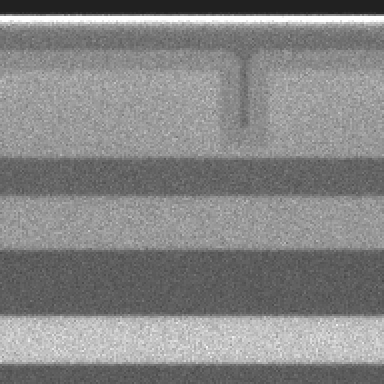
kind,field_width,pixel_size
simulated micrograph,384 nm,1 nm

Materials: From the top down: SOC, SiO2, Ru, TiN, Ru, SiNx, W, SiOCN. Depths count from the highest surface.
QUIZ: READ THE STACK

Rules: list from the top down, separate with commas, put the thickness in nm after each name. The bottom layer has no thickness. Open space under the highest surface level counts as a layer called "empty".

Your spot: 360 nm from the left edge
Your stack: SOC 34, SiO2 20, Ru 88, TiN 38, Ru 54, SiNx 66, W 48, SiOCN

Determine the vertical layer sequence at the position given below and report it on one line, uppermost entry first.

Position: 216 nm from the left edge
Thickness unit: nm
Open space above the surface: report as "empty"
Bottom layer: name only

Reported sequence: SOC 34, SiO2 20, Ru 88, TiN 38, Ru 54, SiNx 66, W 48, SiOCN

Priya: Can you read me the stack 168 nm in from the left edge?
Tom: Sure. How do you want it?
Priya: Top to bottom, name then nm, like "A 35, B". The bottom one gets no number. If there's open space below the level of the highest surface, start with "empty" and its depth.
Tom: SOC 34, SiO2 20, Ru 88, TiN 38, Ru 54, SiNx 66, W 48, SiOCN